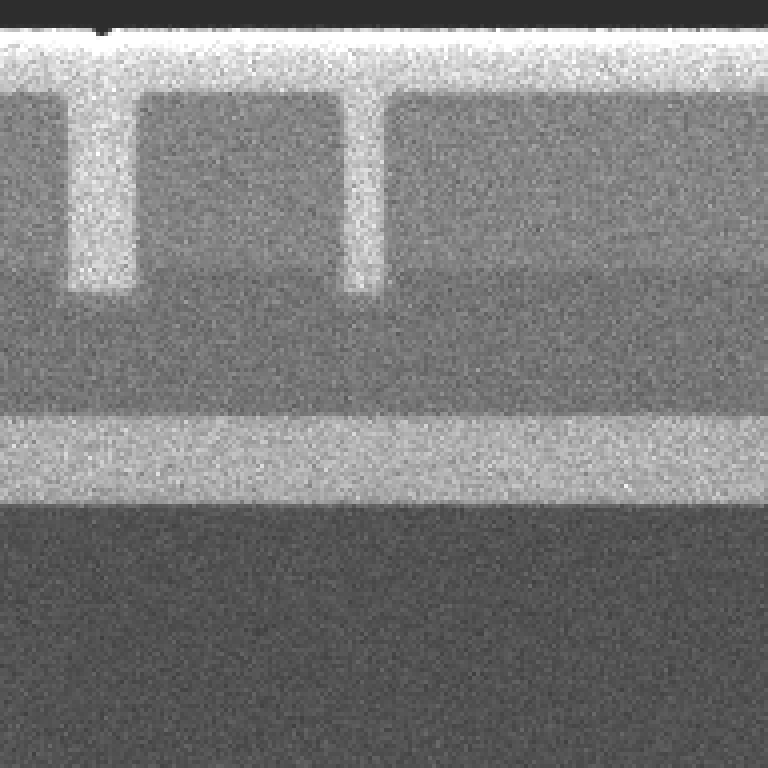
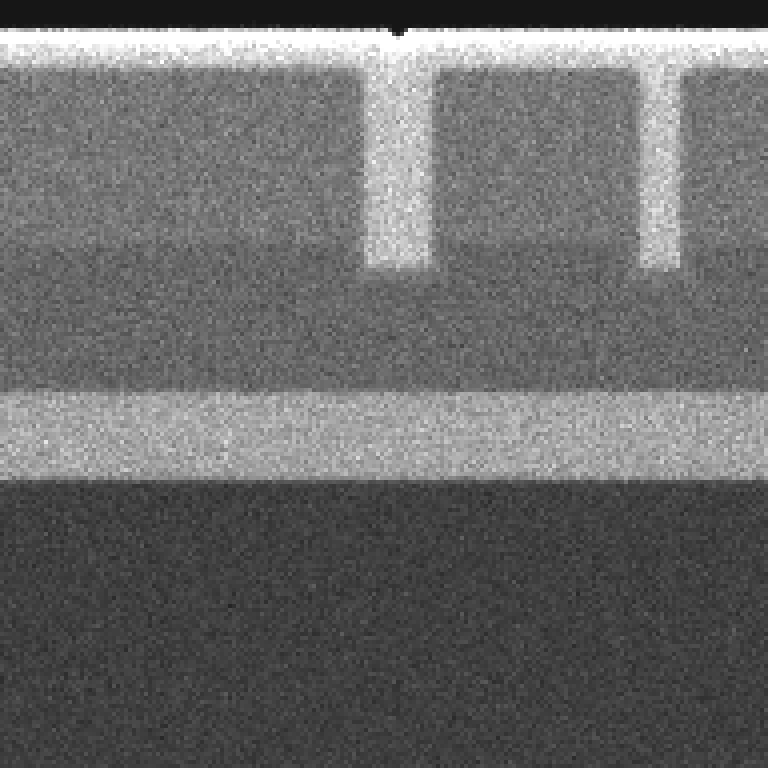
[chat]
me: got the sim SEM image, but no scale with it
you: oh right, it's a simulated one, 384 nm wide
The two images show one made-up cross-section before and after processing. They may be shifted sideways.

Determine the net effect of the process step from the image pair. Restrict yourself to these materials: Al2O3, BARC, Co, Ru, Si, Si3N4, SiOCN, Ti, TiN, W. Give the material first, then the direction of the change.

Ru: removed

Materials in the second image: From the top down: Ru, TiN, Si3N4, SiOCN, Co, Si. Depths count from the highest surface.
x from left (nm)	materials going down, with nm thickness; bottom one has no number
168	Ru 18, TiN 8, Si3N4 80, SiOCN 74, Co 44, Si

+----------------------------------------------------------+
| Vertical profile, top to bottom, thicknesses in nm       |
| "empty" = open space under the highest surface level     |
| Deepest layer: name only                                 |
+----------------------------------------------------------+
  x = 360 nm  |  Ru 18, TiN 8, Si3N4 80, SiOCN 74, Co 44, Si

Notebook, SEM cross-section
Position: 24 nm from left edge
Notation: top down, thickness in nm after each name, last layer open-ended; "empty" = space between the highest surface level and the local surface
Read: Ru 18, TiN 8, Si3N4 80, SiOCN 74, Co 44, Si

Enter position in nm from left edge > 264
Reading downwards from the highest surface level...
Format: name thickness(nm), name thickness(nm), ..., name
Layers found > Ru 18, TiN 8, Si3N4 80, SiOCN 74, Co 44, Si